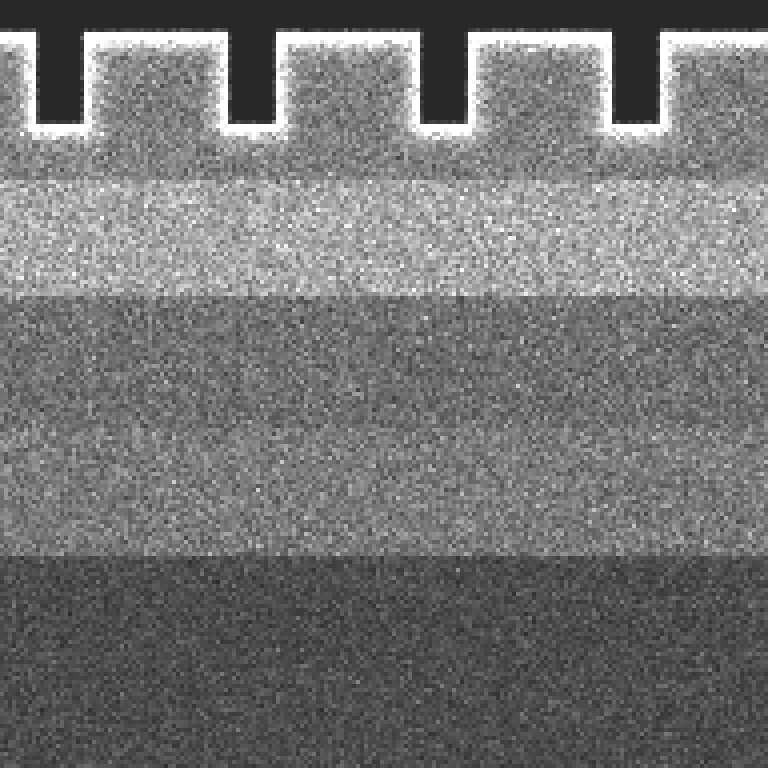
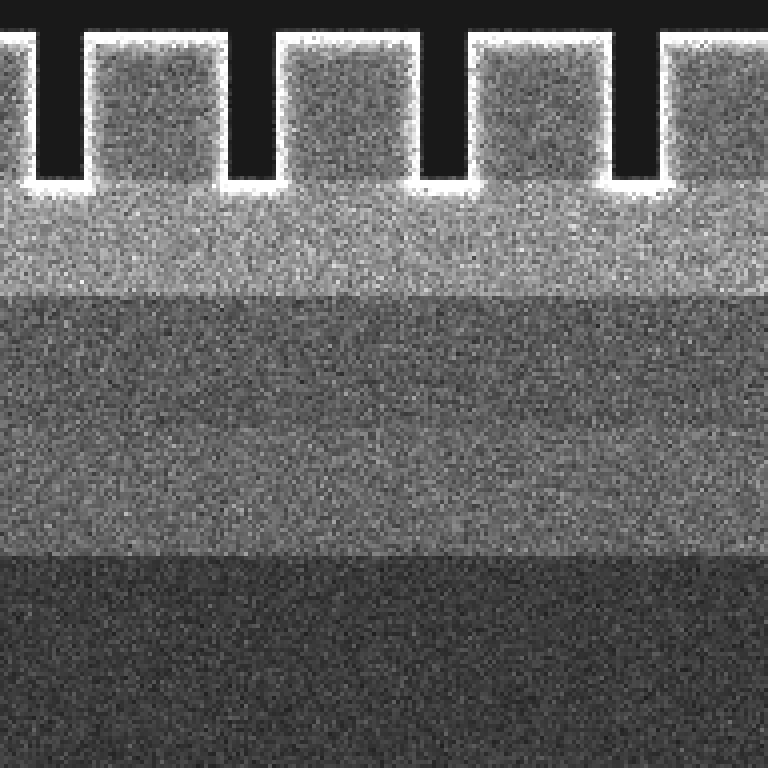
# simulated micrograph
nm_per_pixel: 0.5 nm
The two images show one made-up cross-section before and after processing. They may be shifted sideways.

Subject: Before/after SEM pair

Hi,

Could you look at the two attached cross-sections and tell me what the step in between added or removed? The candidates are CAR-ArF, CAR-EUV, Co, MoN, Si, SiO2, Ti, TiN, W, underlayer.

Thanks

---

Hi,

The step removed underlayer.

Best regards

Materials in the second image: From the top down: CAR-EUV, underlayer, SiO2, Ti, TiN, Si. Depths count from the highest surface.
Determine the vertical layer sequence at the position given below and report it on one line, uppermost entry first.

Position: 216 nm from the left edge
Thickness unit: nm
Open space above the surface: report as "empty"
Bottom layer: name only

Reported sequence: empty 74, SiO2 58, Ti 66, TiN 64, Si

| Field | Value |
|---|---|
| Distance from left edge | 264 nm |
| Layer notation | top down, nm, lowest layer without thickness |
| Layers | CAR-EUV 46, underlayer 28, SiO2 58, Ti 66, TiN 64, Si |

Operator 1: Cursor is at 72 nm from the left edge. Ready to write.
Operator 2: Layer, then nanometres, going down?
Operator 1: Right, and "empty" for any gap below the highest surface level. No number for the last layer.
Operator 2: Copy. CAR-EUV 46, underlayer 28, SiO2 58, Ti 66, TiN 64, Si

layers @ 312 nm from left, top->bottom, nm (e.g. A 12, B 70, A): empty 74, SiO2 58, Ti 66, TiN 64, Si